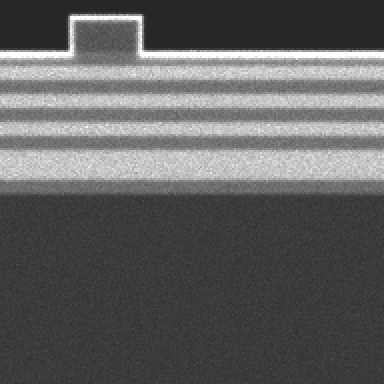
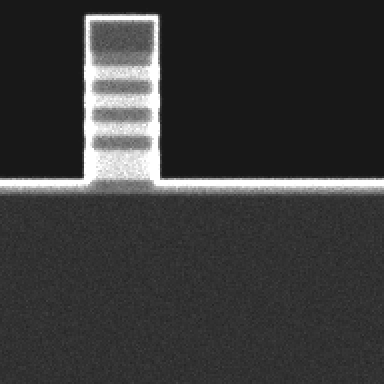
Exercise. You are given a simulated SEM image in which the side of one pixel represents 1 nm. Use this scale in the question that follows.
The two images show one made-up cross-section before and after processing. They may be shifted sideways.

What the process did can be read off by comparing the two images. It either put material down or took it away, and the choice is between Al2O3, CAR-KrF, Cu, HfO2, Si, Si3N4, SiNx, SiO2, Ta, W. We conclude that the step removed Al2O3 and HfO2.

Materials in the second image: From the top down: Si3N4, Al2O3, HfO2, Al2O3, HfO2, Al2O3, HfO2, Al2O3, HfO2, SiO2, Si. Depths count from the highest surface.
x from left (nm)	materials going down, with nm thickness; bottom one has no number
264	empty 164, SiO2 14, Si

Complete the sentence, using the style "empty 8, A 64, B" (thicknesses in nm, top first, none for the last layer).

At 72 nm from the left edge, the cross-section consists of empty 164, SiO2 14, Si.